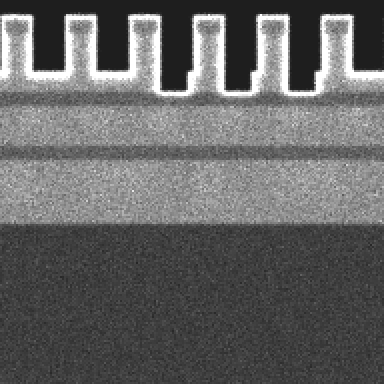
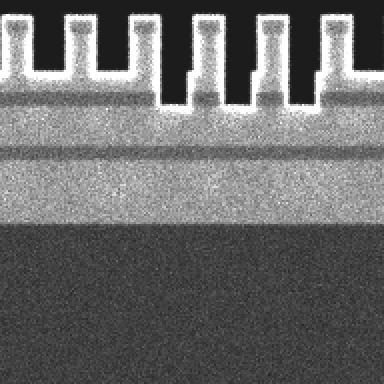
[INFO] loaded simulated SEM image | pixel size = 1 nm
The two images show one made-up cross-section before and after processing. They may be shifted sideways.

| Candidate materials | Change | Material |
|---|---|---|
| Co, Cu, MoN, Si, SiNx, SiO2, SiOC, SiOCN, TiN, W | removed | SiNx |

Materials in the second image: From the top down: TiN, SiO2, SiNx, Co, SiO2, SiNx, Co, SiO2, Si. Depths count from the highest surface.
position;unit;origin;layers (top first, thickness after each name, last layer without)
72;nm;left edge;TiN 18, SiO2 58, SiNx 14, SiO2 40, SiNx 14, SiO2 64, Si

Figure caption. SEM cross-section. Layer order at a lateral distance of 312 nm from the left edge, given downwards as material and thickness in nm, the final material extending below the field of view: empty 90, SiO2 40, SiNx 14, Co 44, SiO2 20, Si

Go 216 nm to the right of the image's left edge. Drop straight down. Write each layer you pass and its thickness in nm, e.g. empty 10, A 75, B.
TiN 18, SiO2 58, SiNx 14, Co 24, SiO2 16, SiNx 14, Co 44, SiO2 20, Si